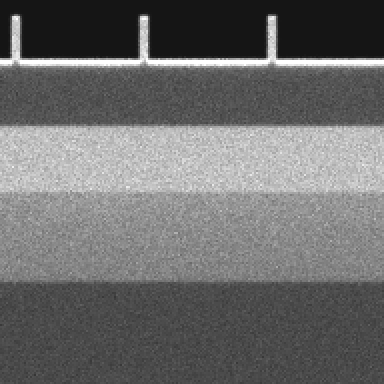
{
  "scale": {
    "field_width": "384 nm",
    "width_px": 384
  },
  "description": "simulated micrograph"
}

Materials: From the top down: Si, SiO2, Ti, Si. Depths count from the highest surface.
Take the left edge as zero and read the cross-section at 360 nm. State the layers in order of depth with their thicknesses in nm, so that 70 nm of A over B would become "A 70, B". empty 44, Si 66, SiO2 66, Ti 90, Si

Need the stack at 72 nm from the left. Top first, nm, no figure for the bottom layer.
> empty 44, Si 66, SiO2 66, Ti 90, Si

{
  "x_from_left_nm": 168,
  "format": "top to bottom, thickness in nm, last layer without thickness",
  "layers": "empty 44, Si 66, SiO2 66, Ti 90, Si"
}